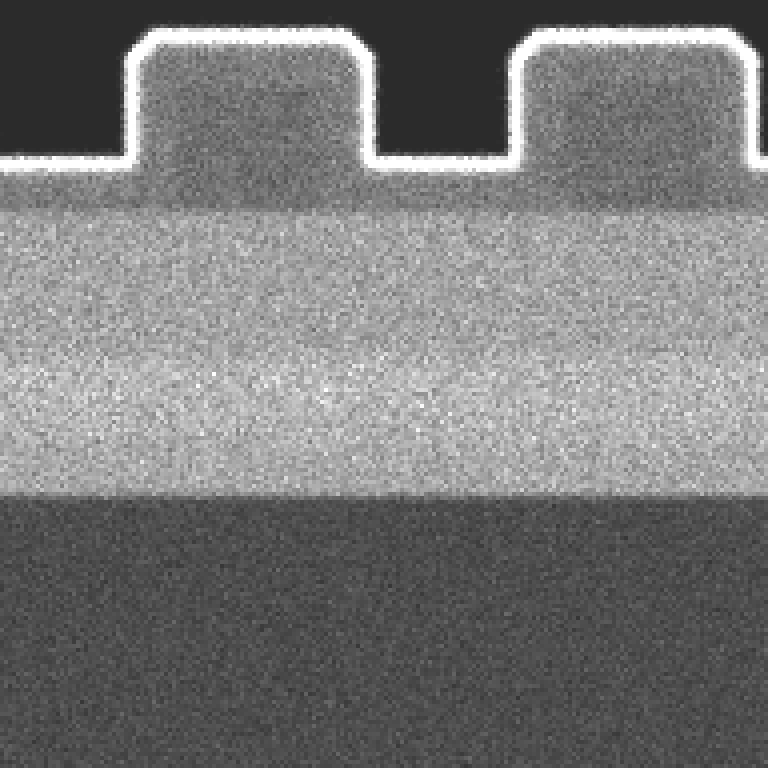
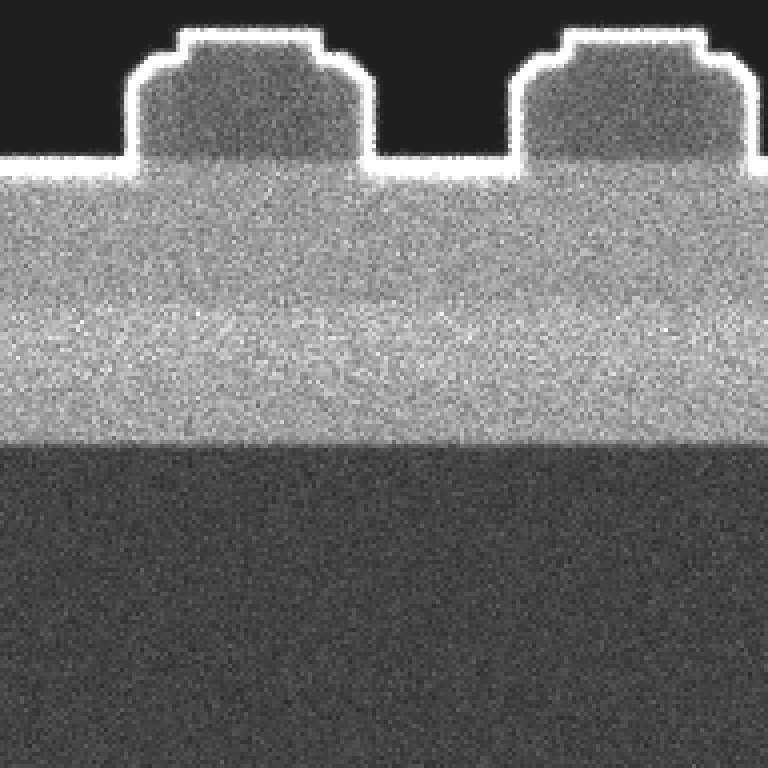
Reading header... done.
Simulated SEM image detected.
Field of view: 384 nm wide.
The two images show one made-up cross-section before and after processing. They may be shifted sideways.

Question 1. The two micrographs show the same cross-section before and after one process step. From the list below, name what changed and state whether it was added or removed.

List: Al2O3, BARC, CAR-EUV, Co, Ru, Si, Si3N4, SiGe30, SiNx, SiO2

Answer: Si3N4, removed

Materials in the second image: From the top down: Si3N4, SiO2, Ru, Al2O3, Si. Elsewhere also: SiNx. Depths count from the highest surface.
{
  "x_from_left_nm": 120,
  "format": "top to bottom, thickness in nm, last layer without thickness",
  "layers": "SiNx 64, SiO2 72, Ru 44, Al2O3 26, Si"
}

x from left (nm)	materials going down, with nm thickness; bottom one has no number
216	empty 64, SiO2 72, Ru 44, Al2O3 26, Si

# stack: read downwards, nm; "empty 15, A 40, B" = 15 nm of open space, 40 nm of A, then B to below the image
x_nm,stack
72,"empty 16, Si3N4 48, SiO2 72, Ru 44, Al2O3 26, Si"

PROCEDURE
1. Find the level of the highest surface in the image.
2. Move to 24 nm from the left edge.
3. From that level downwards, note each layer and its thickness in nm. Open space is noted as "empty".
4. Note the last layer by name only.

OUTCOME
empty 64, SiO2 72, Ru 44, Al2O3 26, Si